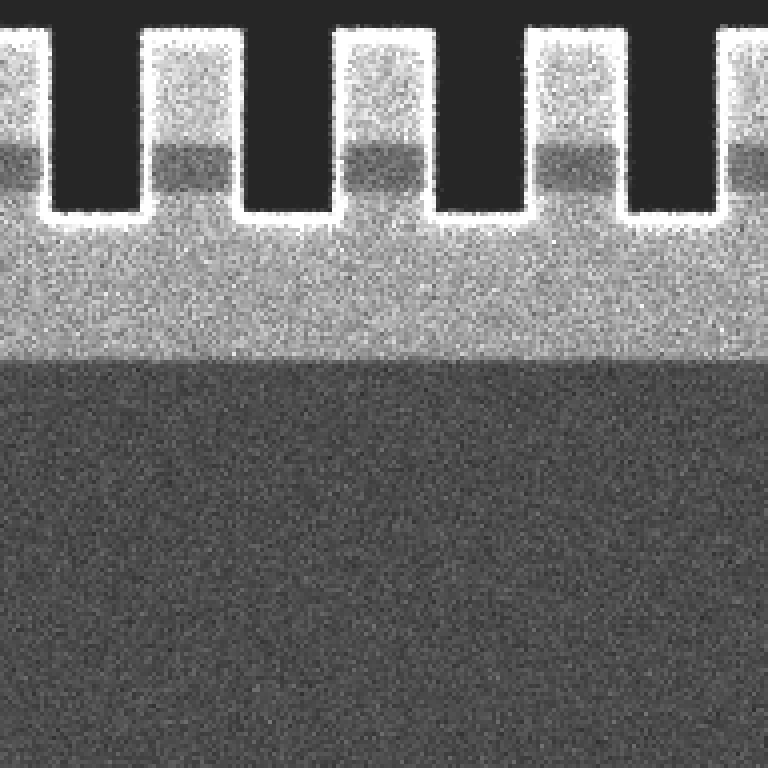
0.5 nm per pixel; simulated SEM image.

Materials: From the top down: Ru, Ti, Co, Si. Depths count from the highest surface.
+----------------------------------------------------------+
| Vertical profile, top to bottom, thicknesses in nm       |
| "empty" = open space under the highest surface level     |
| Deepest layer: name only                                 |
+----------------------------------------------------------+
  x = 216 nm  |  empty 92, Co 72, Si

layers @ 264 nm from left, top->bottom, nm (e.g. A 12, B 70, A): Ru 56, Ti 24, Co 84, Si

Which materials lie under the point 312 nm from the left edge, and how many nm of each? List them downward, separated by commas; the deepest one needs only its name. empty 92, Co 72, Si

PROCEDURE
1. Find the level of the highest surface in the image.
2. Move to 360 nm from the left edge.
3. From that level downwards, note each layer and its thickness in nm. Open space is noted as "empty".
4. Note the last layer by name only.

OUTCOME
Ru 56, Ti 24, Co 84, Si